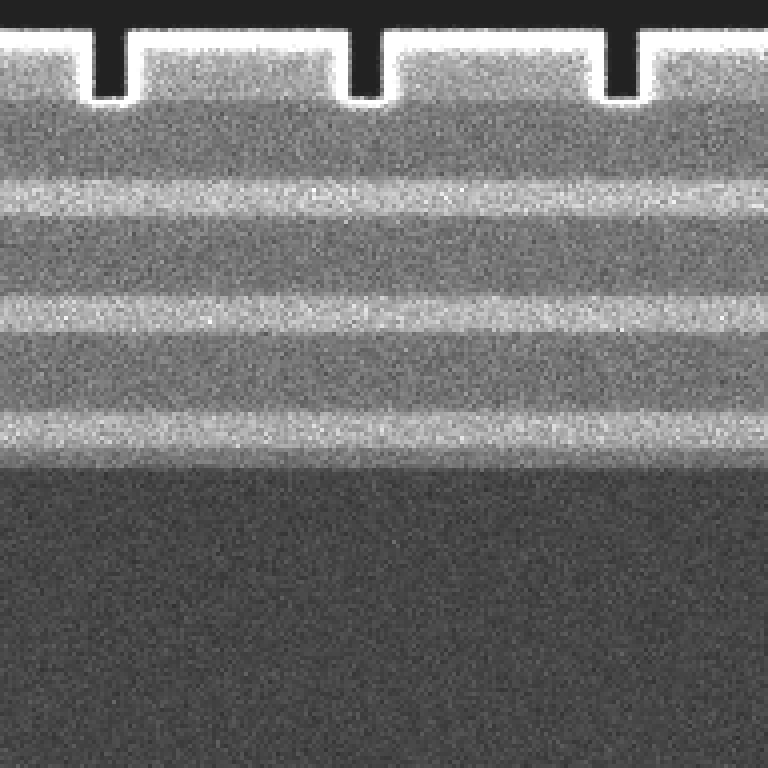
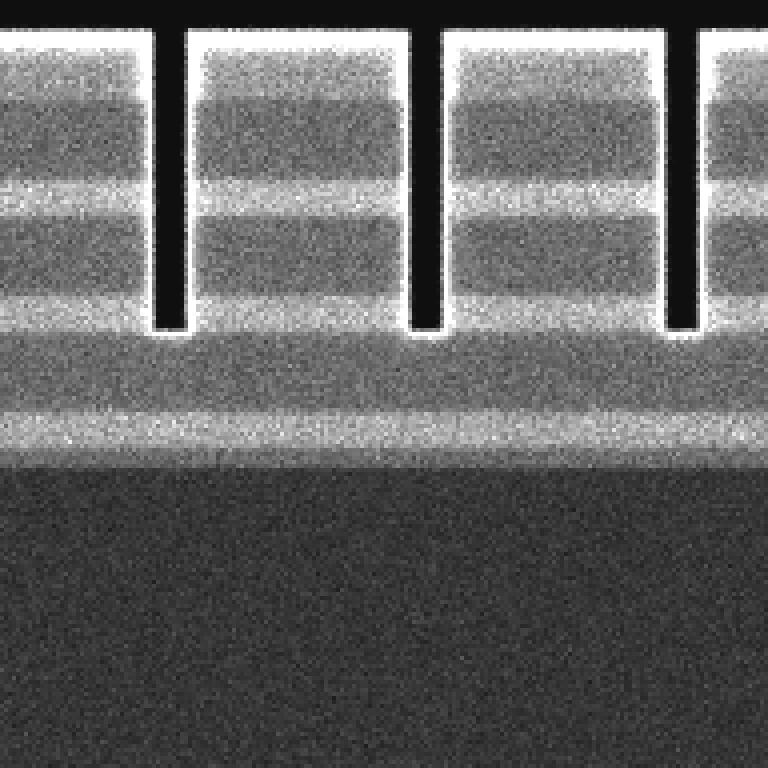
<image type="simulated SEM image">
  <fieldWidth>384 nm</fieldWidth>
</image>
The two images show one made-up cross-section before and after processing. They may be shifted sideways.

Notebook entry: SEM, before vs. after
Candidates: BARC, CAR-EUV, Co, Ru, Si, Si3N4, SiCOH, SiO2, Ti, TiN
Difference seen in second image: Ru and TiN removed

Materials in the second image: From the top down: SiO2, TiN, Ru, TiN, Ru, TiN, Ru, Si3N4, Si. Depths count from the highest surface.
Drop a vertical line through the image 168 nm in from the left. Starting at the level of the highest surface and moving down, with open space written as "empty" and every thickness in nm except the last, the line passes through SiO2 34, TiN 40, Ru 18, TiN 40, Ru 18, TiN 40, Ru 18, Si3N4 10, Si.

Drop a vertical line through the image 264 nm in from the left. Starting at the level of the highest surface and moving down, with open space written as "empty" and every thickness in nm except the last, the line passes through SiO2 34, TiN 40, Ru 18, TiN 40, Ru 18, TiN 40, Ru 18, Si3N4 10, Si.